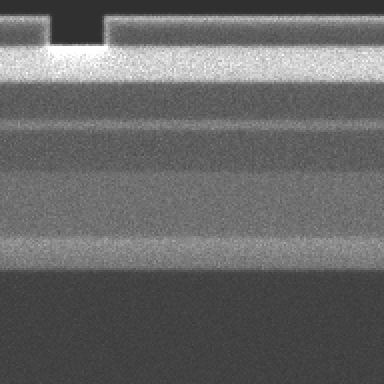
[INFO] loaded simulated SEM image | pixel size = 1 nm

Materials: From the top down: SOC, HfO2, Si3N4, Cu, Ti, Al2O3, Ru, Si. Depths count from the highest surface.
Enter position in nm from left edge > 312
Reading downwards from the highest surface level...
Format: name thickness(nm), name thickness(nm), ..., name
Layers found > SOC 30, HfO2 36, Si3N4 38, Cu 10, Ti 42, Al2O3 66, Ru 32, Si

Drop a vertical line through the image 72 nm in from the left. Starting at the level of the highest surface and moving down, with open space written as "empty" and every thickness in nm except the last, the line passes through empty 30, HfO2 36, Si3N4 38, Cu 10, Ti 42, Al2O3 66, Ru 32, Si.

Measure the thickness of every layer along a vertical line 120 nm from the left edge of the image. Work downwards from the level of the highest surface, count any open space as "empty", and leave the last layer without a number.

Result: SOC 30, HfO2 36, Si3N4 38, Cu 10, Ti 42, Al2O3 66, Ru 32, Si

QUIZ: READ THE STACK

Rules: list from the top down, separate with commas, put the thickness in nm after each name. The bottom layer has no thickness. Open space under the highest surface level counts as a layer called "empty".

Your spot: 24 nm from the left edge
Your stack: SOC 30, HfO2 36, Si3N4 38, Cu 10, Ti 42, Al2O3 66, Ru 32, Si